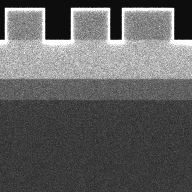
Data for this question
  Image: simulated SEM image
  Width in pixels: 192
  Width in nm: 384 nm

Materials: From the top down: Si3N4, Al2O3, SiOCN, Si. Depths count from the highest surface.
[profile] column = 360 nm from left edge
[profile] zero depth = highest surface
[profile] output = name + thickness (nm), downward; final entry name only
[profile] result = empty 64, Al2O3 78, SiOCN 42, Si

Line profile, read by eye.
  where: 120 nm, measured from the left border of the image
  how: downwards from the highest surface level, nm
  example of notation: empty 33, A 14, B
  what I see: empty 64, Al2O3 78, SiOCN 42, Si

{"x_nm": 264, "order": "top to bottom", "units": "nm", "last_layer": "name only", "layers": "Si3N4 64, Al2O3 78, SiOCN 42, Si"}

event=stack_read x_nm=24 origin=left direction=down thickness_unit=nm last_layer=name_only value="Si3N4 64, Al2O3 78, SiOCN 42, Si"